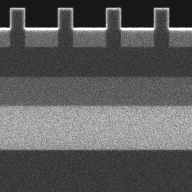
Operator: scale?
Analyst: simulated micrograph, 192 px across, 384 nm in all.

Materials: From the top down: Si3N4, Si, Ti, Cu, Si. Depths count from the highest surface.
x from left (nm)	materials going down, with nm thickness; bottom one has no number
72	empty 40, Si3N4 38, Si 60, Ti 58, Cu 88, Si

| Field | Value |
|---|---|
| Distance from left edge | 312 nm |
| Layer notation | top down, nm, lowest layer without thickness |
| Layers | Si 138, Ti 58, Cu 88, Si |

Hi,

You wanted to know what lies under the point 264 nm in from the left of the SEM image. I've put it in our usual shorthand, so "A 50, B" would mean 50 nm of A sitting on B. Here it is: empty 40, Si3N4 38, Si 60, Ti 58, Cu 88, Si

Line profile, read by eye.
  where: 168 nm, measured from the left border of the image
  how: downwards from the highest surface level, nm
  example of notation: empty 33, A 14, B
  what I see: empty 40, Si3N4 38, Si 60, Ti 58, Cu 88, Si